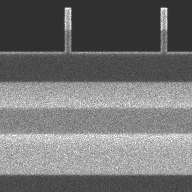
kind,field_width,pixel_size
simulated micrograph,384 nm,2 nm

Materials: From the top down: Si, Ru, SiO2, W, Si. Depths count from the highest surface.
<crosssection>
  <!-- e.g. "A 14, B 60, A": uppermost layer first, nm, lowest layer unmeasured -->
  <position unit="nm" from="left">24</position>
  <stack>empty 88, Si 60, Ru 52, SiO2 52, W 82, Si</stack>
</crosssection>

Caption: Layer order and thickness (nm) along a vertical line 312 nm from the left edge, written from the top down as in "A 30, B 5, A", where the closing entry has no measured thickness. empty 88, Si 60, Ru 52, SiO2 52, W 82, Si